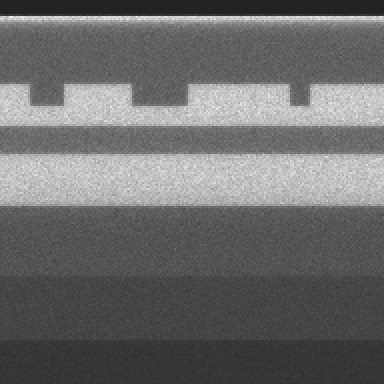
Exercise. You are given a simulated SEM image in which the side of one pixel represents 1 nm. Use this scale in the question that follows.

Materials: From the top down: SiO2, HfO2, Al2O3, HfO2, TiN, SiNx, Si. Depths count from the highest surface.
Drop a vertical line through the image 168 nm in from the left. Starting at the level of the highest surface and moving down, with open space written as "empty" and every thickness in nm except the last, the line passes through SiO2 90, HfO2 20, Al2O3 28, HfO2 52, TiN 70, SiNx 64, Si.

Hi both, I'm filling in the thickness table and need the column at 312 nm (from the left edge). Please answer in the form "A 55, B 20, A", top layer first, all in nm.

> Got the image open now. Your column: SiO2 68, HfO2 42, Al2O3 28, HfO2 52, TiN 70, SiNx 64, Si